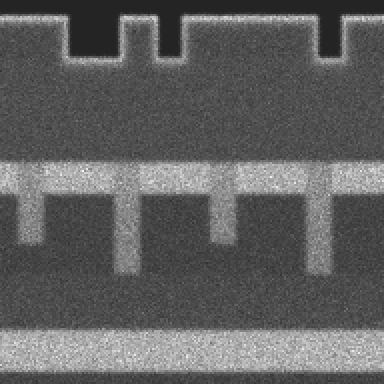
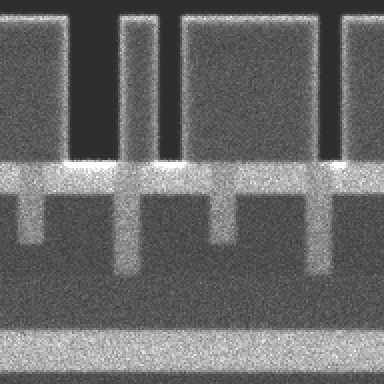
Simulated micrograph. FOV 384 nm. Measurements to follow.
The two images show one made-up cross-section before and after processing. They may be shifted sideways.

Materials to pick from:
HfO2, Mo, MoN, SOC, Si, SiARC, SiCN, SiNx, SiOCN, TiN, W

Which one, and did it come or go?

SOC - removed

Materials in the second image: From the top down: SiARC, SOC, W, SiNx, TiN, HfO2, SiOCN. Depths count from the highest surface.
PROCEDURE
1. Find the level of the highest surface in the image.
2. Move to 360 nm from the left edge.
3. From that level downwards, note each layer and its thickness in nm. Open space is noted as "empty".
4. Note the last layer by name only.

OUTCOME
SiARC 42, SOC 104, HfO2 32, SiNx 80, TiN 56, HfO2 42, SiOCN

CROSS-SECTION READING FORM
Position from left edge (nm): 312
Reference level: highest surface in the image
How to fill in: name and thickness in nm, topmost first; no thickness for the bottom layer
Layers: SiARC 42, SOC 104, W 112, TiN 56, HfO2 42, SiOCN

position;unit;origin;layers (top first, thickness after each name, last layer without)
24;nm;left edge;SiARC 42, SOC 104, W 82, SiNx 30, TiN 56, HfO2 42, SiOCN